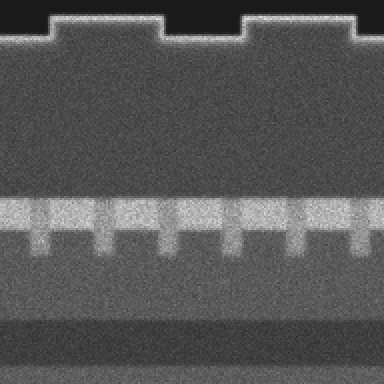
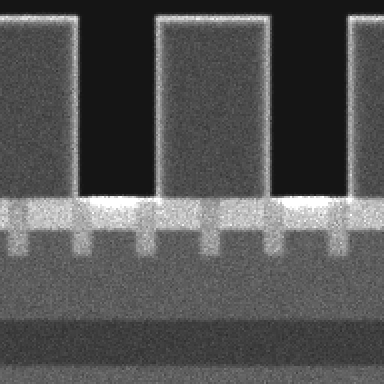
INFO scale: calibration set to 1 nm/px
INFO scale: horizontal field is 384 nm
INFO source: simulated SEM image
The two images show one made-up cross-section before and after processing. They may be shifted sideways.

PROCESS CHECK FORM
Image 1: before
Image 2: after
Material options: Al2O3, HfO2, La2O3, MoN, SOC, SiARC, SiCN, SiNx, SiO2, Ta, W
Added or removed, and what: removed, SOC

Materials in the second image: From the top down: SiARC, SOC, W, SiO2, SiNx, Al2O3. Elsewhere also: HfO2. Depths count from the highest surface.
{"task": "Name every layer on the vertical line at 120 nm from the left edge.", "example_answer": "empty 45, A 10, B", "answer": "empty 182, HfO2 32, SiO2 90, SiNx 46, Al2O3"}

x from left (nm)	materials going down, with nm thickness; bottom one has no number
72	SiARC 20, SOC 162, W 58, SiO2 64, SiNx 46, Al2O3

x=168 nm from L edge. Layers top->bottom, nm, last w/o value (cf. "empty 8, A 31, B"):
SiARC 20, SOC 162, HfO2 32, SiO2 90, SiNx 46, Al2O3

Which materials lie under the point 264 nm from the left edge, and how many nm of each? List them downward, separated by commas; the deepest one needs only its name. SiARC 20, SOC 162, W 58, SiO2 64, SiNx 46, Al2O3